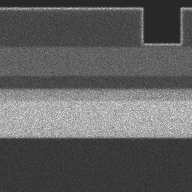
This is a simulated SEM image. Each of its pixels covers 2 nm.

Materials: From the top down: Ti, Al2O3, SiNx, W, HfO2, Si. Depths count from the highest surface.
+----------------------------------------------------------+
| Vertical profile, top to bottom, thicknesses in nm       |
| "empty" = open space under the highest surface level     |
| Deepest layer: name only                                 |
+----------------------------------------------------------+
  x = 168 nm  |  Ti 78, Al2O3 58, SiNx 26, W 24, HfO2 74, Si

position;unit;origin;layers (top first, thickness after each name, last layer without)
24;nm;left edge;Ti 78, Al2O3 58, SiNx 26, W 24, HfO2 74, Si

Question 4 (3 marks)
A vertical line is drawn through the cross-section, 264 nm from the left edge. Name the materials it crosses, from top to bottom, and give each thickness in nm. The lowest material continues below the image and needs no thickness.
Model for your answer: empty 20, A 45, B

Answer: Ti 78, Al2O3 58, SiNx 26, W 24, HfO2 74, Si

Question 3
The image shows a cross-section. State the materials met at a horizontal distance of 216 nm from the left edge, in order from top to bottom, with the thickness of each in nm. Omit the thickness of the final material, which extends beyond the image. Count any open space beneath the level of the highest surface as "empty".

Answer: Ti 78, Al2O3 58, SiNx 26, W 24, HfO2 74, Si